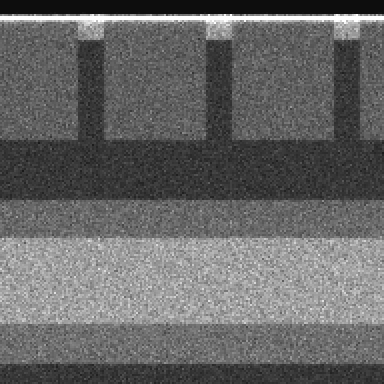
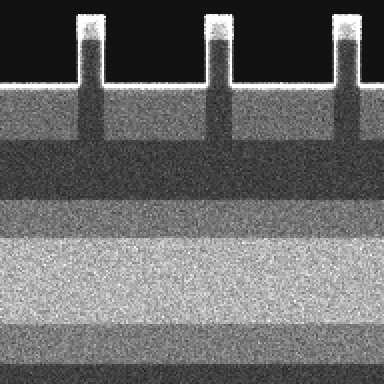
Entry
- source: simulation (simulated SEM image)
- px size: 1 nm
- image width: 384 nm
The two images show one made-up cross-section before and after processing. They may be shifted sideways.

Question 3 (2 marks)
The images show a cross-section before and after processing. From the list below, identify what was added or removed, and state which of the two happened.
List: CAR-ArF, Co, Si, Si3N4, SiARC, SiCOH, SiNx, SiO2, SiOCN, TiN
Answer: SiNx was removed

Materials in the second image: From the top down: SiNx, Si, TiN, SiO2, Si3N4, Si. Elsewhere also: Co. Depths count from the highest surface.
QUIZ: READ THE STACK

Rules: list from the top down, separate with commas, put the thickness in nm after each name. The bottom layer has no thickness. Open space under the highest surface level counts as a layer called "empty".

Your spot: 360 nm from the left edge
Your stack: empty 68, SiNx 56, Si 60, TiN 38, SiO2 86, Si3N4 40, Si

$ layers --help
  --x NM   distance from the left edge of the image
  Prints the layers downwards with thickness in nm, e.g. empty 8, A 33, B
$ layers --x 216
Co 24, Si 160, TiN 38, SiO2 86, Si3N4 40, Si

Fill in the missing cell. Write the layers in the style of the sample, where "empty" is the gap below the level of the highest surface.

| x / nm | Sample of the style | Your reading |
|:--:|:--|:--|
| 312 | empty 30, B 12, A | empty 68, SiNx 56, Si 60, TiN 38, SiO2 86, Si3N4 40, Si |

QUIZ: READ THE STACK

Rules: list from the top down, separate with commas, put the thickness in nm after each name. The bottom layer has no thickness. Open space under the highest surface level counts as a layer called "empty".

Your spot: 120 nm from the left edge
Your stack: empty 68, SiNx 56, Si 60, TiN 38, SiO2 86, Si3N4 40, Si